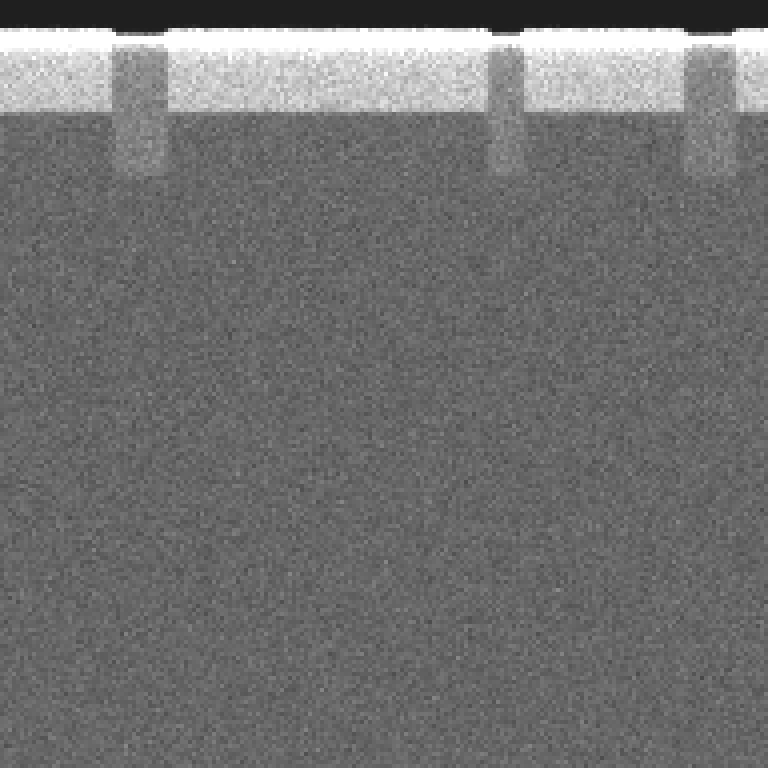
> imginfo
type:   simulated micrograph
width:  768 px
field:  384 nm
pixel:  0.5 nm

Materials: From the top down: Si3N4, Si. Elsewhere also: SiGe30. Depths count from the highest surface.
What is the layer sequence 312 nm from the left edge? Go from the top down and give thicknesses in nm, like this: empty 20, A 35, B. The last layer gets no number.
Si3N4 40, Si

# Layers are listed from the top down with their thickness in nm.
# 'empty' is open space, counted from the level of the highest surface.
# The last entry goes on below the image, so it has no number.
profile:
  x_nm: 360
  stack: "empty 2, SiGe30 70, Si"